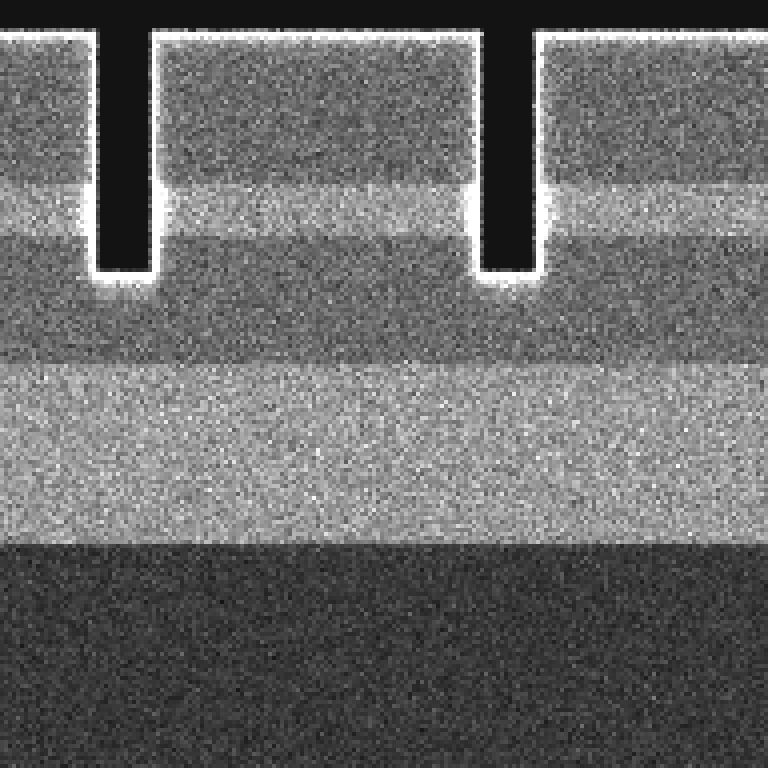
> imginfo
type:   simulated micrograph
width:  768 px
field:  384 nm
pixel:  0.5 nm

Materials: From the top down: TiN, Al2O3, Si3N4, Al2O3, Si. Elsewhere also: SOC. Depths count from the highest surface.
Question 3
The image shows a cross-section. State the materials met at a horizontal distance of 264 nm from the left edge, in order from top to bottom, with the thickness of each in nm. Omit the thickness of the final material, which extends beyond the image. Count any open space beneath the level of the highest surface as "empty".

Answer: empty 120, SOC 12, Si3N4 34, Al2O3 90, Si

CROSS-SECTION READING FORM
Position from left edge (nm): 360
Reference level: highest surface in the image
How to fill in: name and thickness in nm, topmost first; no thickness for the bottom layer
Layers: TiN 76, Al2O3 26, Si3N4 64, Al2O3 90, Si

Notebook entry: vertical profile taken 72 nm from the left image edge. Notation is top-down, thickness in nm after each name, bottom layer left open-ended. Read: empty 120, SOC 12, Si3N4 34, Al2O3 90, Si